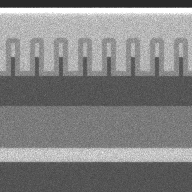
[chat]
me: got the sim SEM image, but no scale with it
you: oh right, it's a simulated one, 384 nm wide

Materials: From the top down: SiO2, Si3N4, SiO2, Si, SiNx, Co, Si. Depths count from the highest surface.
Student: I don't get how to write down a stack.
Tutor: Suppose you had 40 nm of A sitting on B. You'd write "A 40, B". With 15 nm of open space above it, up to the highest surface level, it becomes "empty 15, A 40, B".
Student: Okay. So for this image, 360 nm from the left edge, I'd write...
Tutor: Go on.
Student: SiO2 60, Si3N4 10, SiO2 28, Si 98, SiNx 84, Co 28, Si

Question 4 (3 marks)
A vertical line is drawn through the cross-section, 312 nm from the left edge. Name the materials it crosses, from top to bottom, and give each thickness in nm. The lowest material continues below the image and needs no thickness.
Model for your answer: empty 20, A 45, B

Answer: SiO2 60, Si3N4 10, SiO2 28, Si 98, SiNx 84, Co 28, Si